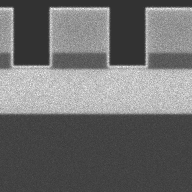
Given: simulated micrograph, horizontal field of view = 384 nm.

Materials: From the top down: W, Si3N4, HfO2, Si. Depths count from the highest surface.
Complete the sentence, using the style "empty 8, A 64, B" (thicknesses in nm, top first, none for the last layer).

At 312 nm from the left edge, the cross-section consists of W 90, Si3N4 32, HfO2 90, Si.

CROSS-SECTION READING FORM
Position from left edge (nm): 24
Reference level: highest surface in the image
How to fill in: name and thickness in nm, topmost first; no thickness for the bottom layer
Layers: W 90, Si3N4 32, HfO2 90, Si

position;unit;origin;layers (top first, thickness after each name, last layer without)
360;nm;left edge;W 90, Si3N4 32, HfO2 90, Si